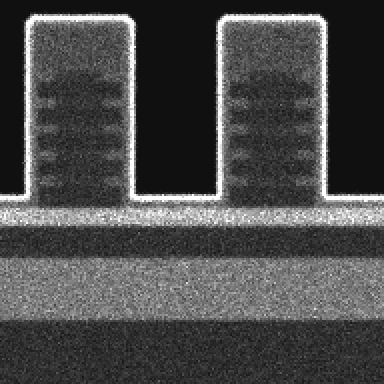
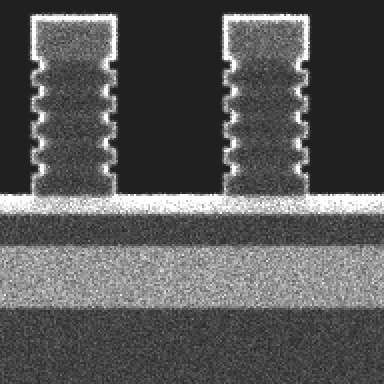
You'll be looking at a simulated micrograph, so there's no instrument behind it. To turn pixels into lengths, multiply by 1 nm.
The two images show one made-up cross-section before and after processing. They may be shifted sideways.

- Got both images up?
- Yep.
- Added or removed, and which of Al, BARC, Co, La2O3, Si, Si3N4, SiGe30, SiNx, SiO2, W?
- removed, Si3N4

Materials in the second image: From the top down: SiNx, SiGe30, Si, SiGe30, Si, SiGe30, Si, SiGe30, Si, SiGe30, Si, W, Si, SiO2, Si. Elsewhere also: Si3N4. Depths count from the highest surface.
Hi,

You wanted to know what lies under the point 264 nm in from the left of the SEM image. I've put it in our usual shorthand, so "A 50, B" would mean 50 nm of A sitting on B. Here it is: SiNx 44, SiGe30 10, Si 16, SiGe30 10, Si 16, SiGe30 10, Si 16, SiGe30 10, Si 16, SiGe30 10, Si 22, W 18, Si 32, SiO2 62, Si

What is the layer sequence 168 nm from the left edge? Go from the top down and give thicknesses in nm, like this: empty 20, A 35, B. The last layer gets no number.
empty 180, W 18, Si 32, SiO2 62, Si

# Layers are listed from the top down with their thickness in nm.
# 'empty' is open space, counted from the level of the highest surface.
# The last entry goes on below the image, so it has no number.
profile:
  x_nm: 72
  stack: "SiNx 44, SiGe30 10, Si 16, SiGe30 10, Si 16, SiGe30 10, Si 16, SiGe30 10, Si 16, SiGe30 10, Si 22, W 18, Si 32, SiO2 62, Si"